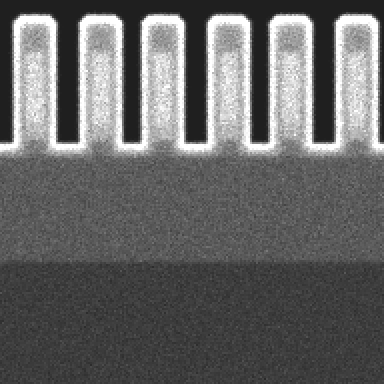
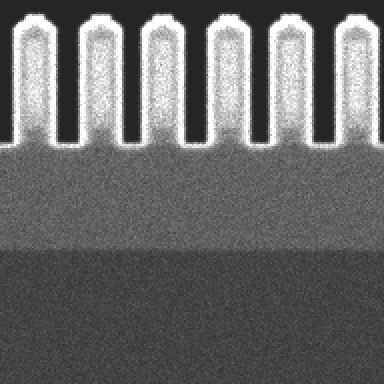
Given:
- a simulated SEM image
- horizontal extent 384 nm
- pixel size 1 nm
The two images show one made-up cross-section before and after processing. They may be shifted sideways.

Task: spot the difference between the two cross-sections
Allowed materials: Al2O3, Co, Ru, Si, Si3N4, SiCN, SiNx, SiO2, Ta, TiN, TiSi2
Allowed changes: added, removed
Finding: removed SiO2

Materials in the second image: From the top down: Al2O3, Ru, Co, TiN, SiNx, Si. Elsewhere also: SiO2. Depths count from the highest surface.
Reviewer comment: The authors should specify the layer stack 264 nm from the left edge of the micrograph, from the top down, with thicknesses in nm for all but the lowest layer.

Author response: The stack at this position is empty 128, SiNx 106, Si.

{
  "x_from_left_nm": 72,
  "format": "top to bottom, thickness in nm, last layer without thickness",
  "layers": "empty 128, SiNx 106, Si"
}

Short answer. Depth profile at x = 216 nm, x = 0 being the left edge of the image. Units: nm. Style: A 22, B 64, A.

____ empty 6, SiO2 122, SiNx 106, Si